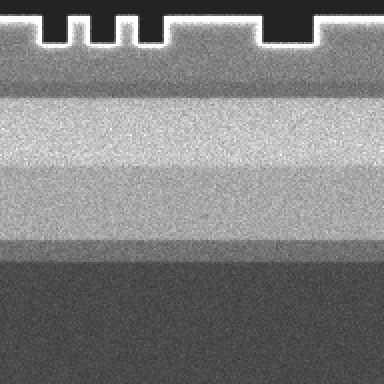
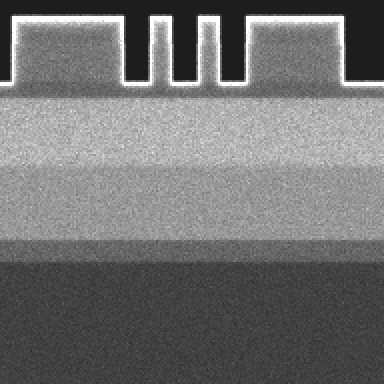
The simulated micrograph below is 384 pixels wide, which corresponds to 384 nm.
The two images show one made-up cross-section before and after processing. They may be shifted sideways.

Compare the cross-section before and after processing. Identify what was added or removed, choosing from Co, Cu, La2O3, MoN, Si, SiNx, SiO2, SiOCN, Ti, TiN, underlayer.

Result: TiN removed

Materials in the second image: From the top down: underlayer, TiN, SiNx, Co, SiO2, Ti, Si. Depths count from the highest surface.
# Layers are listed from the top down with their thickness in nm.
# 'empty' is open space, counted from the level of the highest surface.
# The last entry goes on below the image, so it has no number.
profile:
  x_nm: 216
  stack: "underlayer 28, TiN 38, SiNx 16, Co 68, SiO2 74, Ti 22, Si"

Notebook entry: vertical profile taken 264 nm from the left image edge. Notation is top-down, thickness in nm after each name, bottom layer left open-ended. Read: underlayer 28, TiN 38, SiNx 16, Co 68, SiO2 74, Ti 22, Si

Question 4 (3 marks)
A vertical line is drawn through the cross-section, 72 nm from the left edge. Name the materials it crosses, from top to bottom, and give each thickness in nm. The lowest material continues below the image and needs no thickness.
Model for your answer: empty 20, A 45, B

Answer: underlayer 28, TiN 38, SiNx 16, Co 68, SiO2 74, Ti 22, Si